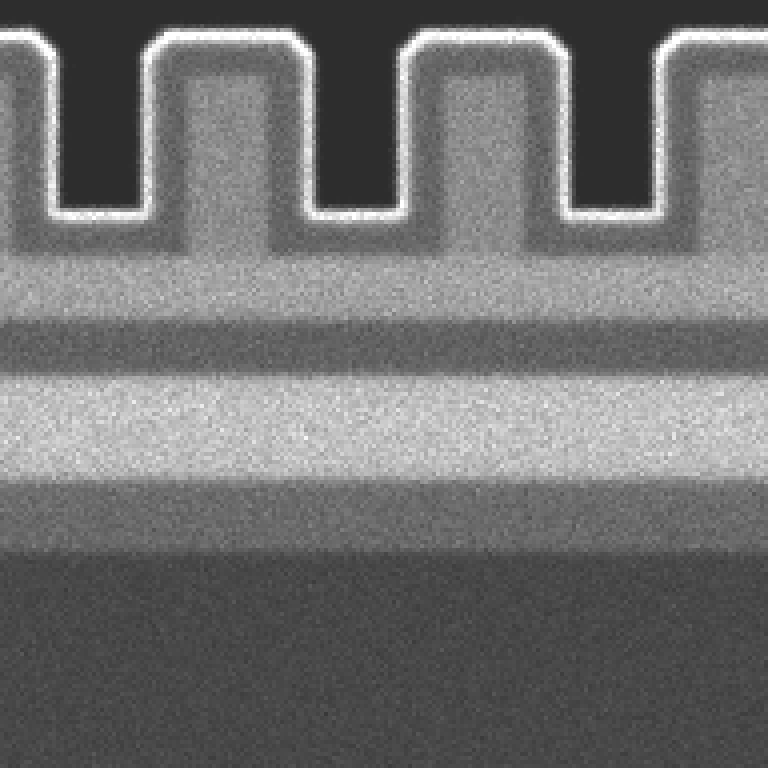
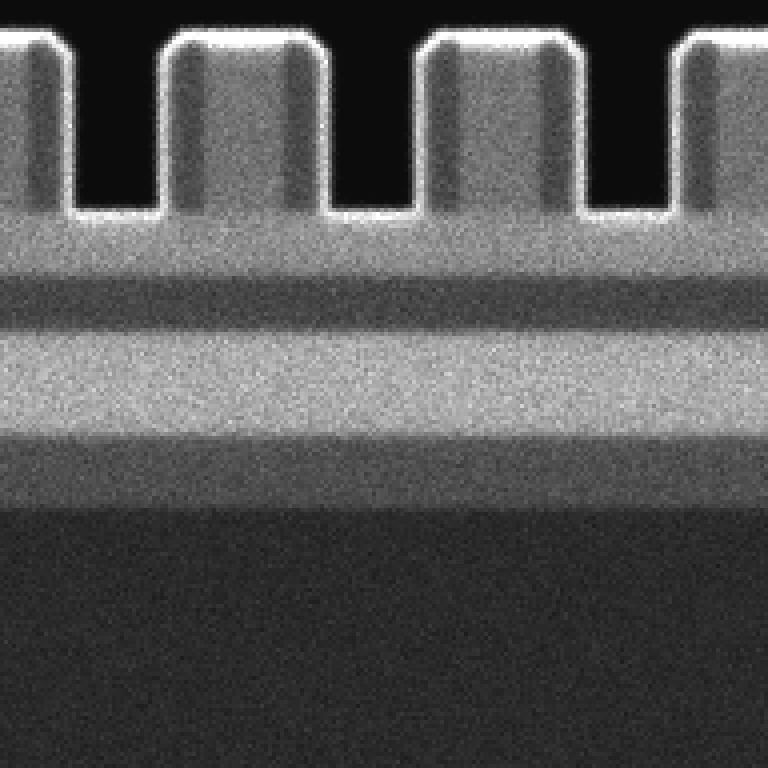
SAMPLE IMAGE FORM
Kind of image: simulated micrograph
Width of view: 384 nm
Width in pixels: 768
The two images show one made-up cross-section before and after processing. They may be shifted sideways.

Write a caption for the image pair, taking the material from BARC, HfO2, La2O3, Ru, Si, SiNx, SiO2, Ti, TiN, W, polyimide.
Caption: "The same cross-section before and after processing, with SiNx removed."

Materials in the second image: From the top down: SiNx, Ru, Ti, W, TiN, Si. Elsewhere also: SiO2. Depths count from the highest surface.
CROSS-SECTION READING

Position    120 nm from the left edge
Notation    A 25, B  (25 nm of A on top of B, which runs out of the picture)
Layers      SiO2 90, Ru 32, Ti 28, W 52, TiN 36, Si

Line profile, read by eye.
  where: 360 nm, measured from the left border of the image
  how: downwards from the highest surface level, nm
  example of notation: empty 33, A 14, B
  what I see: SiO2 90, Ru 32, Ti 28, W 52, TiN 36, Si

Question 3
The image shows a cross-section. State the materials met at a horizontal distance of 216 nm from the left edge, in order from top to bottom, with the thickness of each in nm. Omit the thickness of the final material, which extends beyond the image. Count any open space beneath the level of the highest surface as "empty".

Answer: empty 2, SiNx 88, Ru 32, Ti 28, W 52, TiN 36, Si